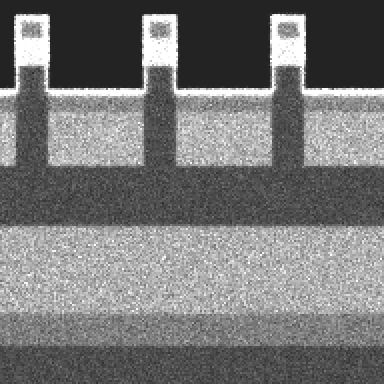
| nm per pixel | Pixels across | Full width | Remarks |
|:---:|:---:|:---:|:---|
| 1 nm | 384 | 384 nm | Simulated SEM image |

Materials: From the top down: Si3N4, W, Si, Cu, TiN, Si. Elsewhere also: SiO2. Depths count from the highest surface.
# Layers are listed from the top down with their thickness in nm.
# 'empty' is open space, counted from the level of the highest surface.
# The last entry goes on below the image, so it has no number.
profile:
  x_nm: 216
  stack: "empty 74, Si3N4 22, SiO2 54, Si 60, Cu 88, TiN 32, Si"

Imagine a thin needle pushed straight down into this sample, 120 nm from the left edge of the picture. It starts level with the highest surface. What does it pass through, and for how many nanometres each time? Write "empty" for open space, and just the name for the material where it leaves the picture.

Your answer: empty 74, Si3N4 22, SiO2 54, Si 60, Cu 88, TiN 32, Si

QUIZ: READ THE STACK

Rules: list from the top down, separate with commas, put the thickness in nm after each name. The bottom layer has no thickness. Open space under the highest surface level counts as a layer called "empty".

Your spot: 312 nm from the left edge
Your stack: empty 74, Si3N4 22, SiO2 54, Si 60, Cu 88, TiN 32, Si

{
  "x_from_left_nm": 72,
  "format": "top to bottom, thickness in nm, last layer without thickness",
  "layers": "empty 74, Si3N4 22, SiO2 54, Si 60, Cu 88, TiN 32, Si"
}